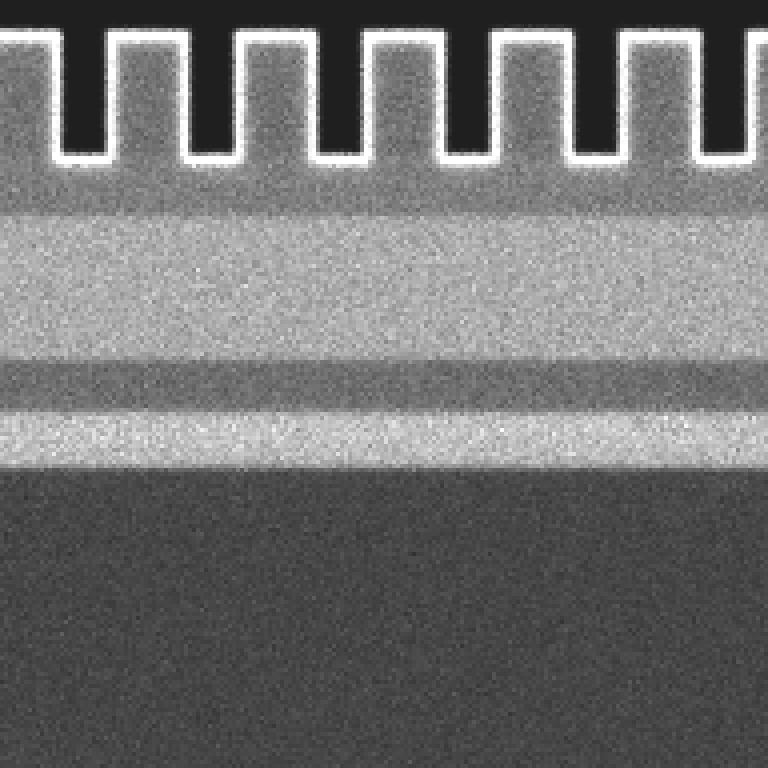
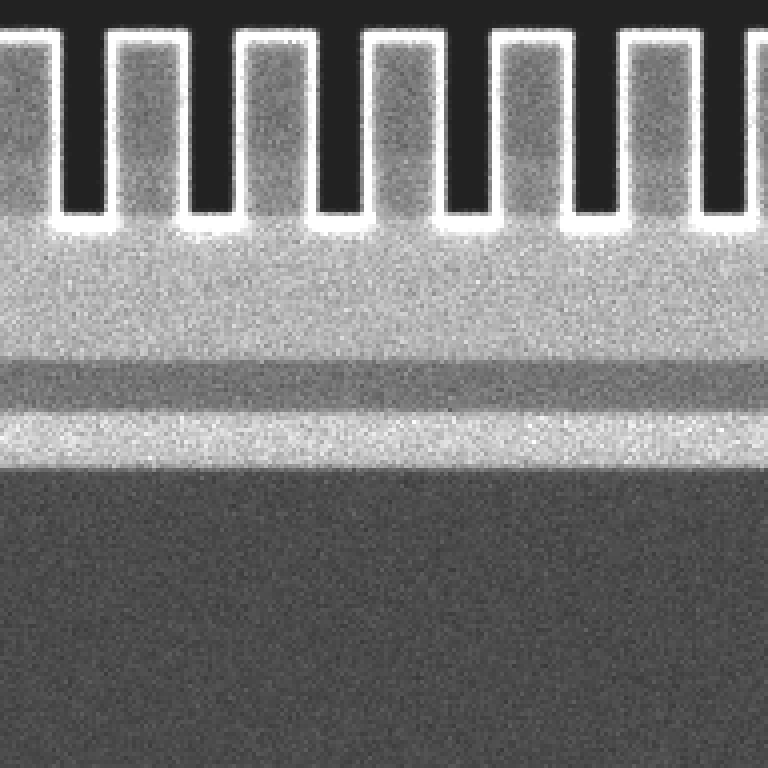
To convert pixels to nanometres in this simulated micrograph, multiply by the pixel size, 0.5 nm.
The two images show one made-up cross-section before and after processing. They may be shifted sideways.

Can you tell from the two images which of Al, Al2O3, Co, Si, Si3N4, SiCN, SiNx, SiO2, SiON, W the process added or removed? Yes, it removed Si3N4.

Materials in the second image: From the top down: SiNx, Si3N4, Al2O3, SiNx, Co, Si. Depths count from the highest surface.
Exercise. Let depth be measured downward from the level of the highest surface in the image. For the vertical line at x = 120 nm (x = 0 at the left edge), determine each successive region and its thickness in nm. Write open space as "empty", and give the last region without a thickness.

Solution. SiNx 62, Si3N4 30, Al2O3 72, SiNx 26, Co 28, Si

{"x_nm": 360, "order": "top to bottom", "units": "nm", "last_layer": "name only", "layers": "empty 92, Al2O3 72, SiNx 26, Co 28, Si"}